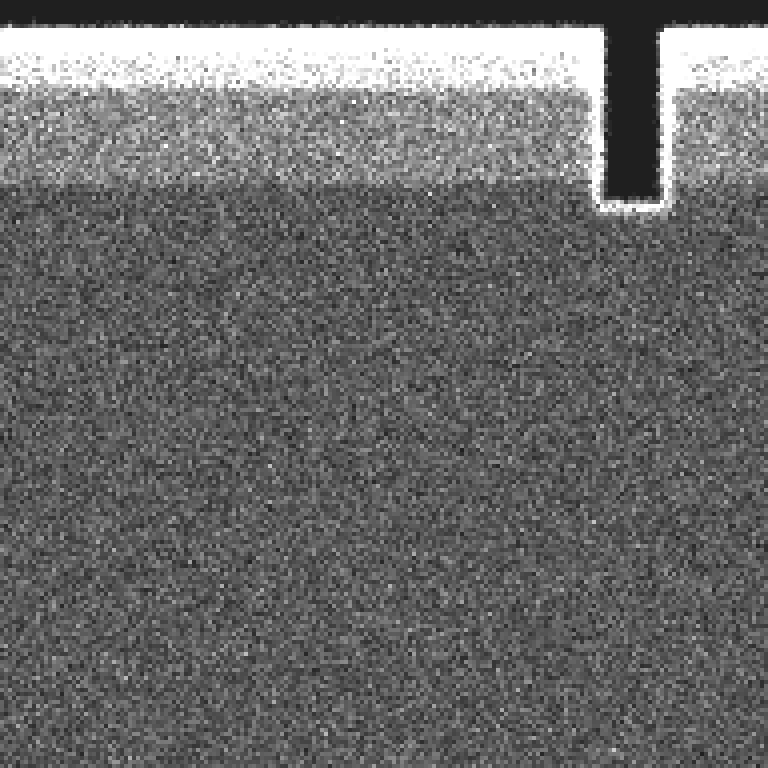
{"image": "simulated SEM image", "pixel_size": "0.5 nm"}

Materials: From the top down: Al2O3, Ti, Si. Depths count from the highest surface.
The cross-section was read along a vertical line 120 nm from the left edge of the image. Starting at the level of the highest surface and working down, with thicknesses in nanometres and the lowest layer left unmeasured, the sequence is Al2O3 28, Ti 48, Si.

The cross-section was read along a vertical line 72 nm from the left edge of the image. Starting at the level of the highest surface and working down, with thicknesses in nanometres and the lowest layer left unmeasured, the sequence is Al2O3 28, Ti 48, Si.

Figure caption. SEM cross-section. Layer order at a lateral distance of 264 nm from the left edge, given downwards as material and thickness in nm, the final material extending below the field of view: Al2O3 28, Ti 48, Si